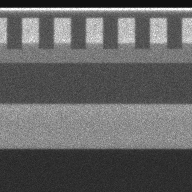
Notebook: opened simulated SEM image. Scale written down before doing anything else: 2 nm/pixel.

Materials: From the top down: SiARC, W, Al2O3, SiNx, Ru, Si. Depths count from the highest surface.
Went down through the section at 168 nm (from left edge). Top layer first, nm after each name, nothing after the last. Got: SiARC 82, Al2O3 28, SiNx 82, Ru 90, Si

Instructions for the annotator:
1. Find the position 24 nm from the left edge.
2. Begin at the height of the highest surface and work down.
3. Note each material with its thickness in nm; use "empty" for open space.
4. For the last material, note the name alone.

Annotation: SiARC 82, Al2O3 28, SiNx 82, Ru 90, Si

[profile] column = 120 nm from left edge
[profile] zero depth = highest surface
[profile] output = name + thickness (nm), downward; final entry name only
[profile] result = SiARC 20, W 50, Al2O3 40, SiNx 82, Ru 90, Si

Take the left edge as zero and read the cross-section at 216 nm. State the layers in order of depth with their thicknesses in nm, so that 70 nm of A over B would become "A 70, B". SiARC 82, Al2O3 28, SiNx 82, Ru 90, Si